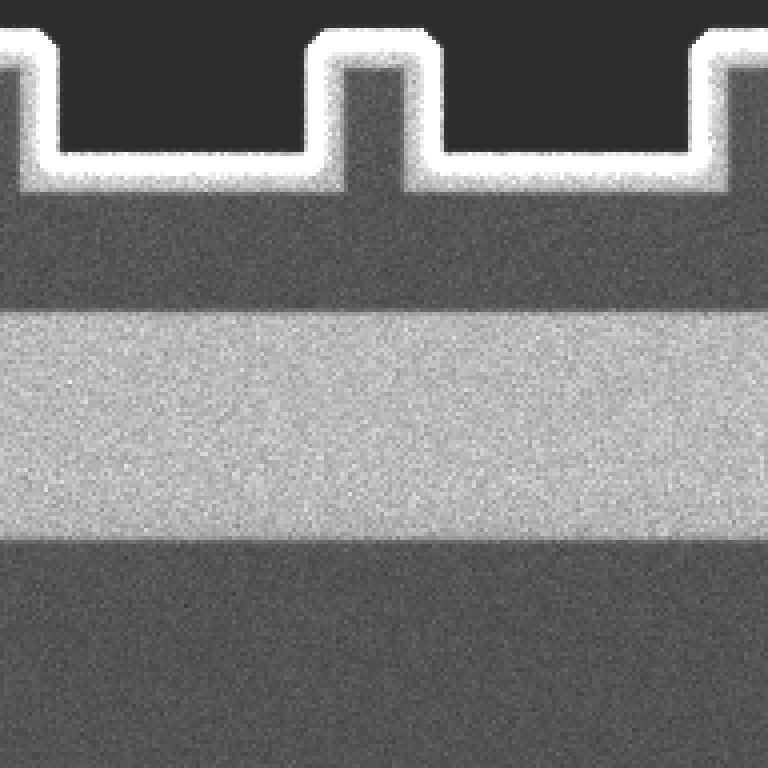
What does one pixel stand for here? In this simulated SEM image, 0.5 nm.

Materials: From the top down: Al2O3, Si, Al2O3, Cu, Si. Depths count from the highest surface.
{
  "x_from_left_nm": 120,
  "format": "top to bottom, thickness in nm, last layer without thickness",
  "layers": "empty 62, Al2O3 18, Si 60, Al2O3 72, Cu 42, Si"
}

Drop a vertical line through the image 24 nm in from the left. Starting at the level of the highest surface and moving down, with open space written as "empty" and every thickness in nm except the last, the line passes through empty 6, Al2O3 74, Si 60, Al2O3 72, Cu 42, Si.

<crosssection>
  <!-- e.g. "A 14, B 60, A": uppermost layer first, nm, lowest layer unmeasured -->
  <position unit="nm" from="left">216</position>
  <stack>empty 6, Al2O3 74, Si 60, Al2O3 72, Cu 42, Si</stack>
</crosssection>